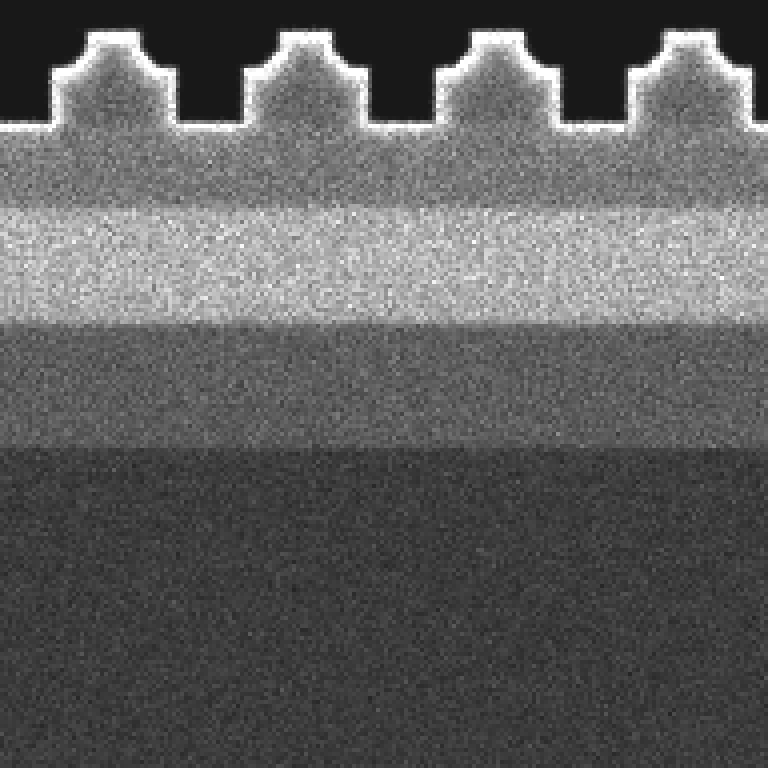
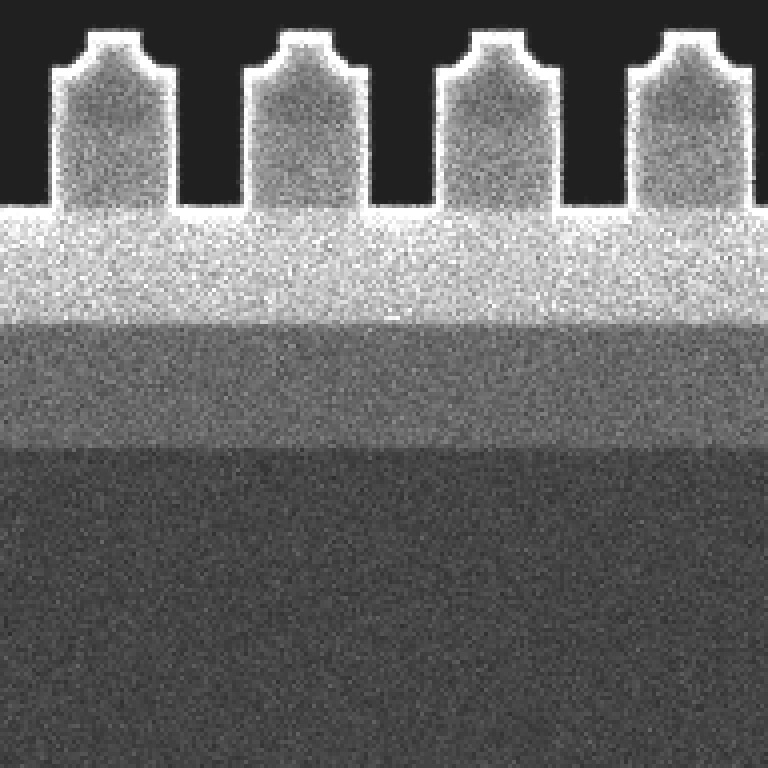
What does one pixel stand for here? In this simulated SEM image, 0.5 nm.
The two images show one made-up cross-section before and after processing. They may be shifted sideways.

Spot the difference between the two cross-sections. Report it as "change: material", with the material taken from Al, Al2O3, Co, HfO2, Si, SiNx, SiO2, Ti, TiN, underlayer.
removed: TiN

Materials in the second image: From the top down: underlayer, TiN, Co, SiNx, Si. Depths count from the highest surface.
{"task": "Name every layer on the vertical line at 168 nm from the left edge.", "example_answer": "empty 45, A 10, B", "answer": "empty 12, underlayer 34, TiN 42, Co 58, SiNx 62, Si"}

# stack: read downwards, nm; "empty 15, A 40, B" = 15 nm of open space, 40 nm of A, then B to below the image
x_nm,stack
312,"empty 88, Co 58, SiNx 62, Si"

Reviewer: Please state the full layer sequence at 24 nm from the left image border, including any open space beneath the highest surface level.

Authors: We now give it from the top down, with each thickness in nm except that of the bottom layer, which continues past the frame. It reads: empty 88, Co 58, SiNx 62, Si